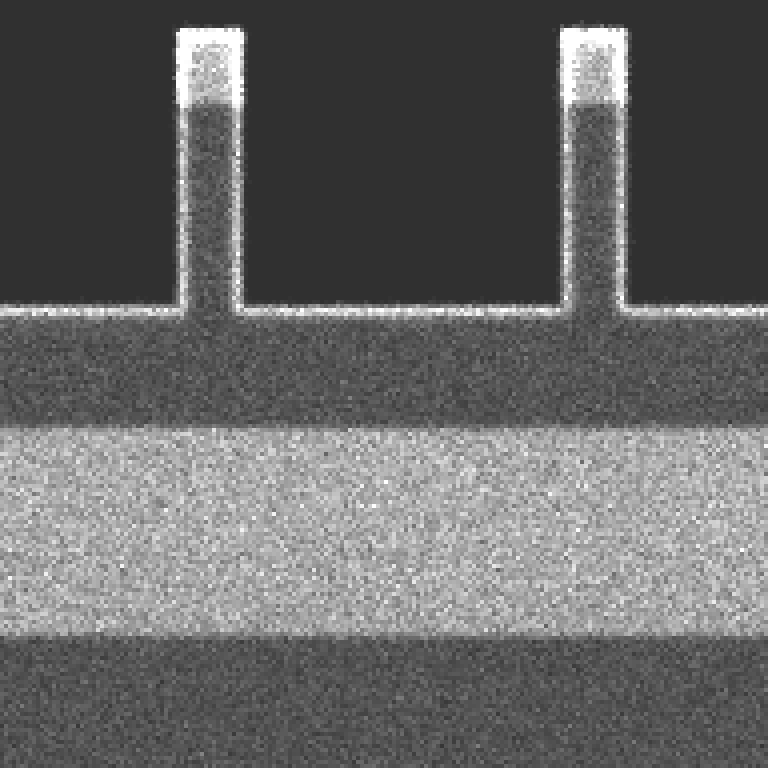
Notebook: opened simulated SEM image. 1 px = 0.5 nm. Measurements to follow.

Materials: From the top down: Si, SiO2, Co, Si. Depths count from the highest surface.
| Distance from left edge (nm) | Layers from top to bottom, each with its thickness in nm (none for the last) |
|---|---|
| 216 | empty 138, Si 60, SiO2 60, Co 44, Si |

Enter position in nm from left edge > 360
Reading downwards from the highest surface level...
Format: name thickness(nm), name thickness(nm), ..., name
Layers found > empty 138, Si 60, SiO2 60, Co 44, Si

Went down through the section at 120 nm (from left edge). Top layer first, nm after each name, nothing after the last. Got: empty 138, Si 60, SiO2 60, Co 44, Si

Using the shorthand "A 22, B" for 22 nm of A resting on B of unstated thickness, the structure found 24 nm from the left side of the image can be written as empty 138, Si 60, SiO2 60, Co 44, Si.